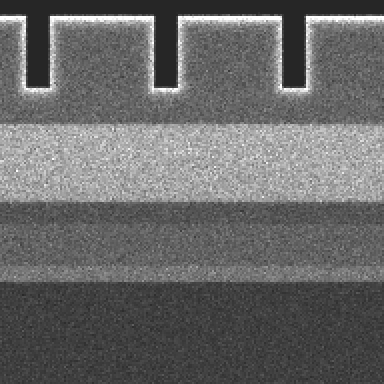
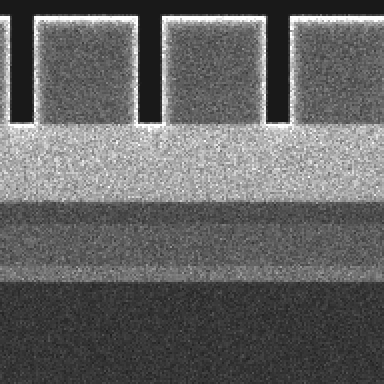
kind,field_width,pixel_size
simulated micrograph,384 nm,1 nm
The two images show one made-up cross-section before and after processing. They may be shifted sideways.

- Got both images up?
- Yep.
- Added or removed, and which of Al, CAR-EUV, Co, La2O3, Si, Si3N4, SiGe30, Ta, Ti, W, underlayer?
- removed, underlayer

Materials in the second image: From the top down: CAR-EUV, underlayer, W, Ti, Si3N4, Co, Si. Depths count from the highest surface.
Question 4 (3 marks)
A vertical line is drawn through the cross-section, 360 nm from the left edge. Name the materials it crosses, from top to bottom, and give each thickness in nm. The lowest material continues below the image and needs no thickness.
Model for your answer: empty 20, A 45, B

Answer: CAR-EUV 72, underlayer 36, W 78, Ti 22, Si3N4 42, Co 16, Si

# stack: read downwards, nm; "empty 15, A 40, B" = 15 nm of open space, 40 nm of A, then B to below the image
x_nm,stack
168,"CAR-EUV 72, underlayer 36, W 78, Ti 22, Si3N4 42, Co 16, Si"